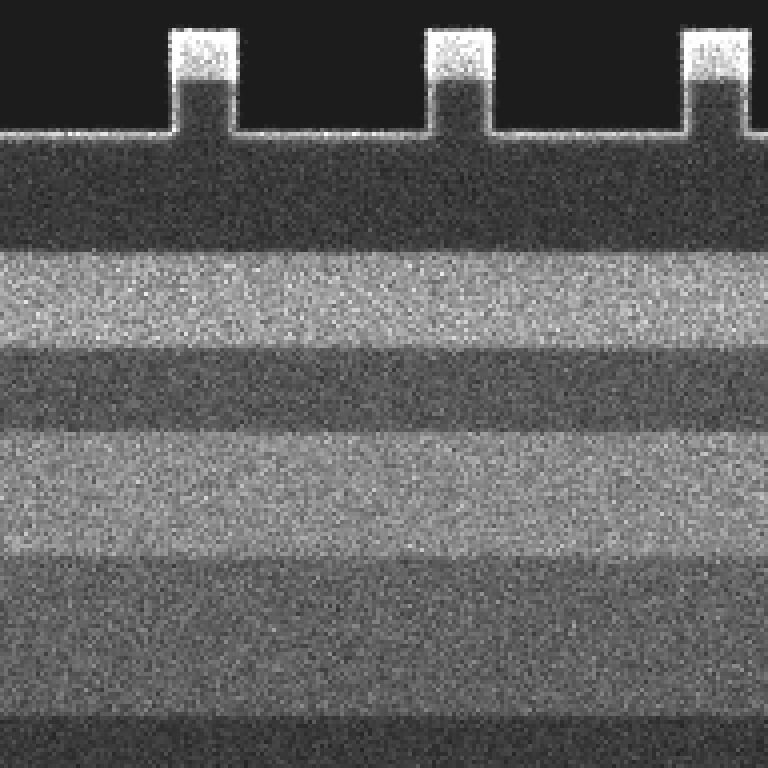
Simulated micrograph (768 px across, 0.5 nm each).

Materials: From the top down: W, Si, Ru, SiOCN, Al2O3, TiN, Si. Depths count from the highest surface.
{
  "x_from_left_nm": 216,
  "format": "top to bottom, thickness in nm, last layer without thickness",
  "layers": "W 24, Si 86, Ru 48, SiOCN 42, Al2O3 62, TiN 80, Si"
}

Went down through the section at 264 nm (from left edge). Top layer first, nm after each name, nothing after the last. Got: empty 50, Si 60, Ru 48, SiOCN 42, Al2O3 62, TiN 80, Si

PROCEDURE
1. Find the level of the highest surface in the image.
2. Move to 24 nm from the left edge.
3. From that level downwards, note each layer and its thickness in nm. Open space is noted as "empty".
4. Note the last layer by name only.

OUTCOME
empty 50, Si 60, Ru 48, SiOCN 42, Al2O3 62, TiN 80, Si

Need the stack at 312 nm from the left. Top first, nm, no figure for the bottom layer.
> empty 50, Si 60, Ru 48, SiOCN 42, Al2O3 62, TiN 80, Si